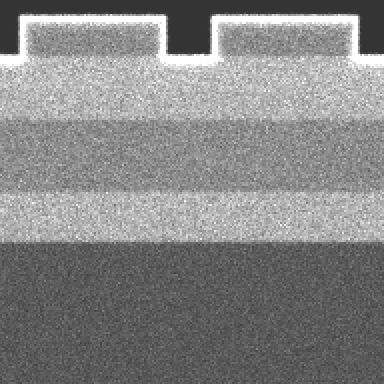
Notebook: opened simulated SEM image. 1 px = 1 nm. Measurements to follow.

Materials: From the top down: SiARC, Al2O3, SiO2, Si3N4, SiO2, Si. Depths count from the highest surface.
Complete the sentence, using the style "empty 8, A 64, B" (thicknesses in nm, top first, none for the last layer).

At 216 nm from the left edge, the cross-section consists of SiARC 40, Al2O3 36, SiO2 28, Si3N4 72, SiO2 50, Si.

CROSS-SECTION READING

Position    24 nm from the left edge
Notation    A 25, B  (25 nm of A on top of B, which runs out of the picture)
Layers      SiARC 40, Al2O3 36, SiO2 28, Si3N4 72, SiO2 50, Si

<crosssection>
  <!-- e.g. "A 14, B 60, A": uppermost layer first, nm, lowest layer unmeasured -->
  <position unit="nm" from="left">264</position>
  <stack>SiARC 40, Al2O3 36, SiO2 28, Si3N4 72, SiO2 50, Si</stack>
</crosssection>